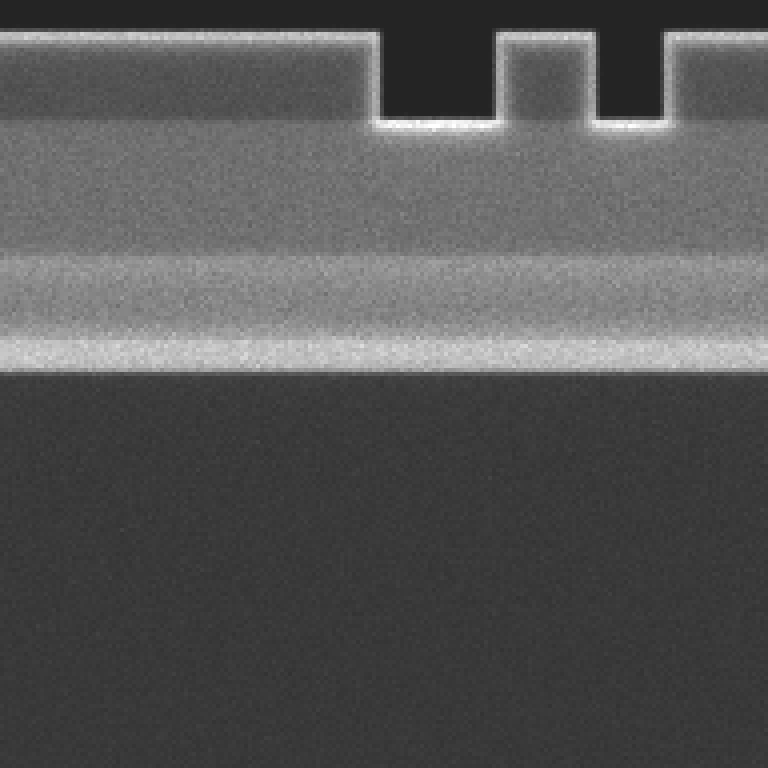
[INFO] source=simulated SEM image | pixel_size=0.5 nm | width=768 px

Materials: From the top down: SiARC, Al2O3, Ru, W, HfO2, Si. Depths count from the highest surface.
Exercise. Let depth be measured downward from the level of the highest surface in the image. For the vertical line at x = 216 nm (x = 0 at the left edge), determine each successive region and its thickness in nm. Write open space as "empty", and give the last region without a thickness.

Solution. empty 44, Al2O3 68, Ru 34, W 8, HfO2 16, Si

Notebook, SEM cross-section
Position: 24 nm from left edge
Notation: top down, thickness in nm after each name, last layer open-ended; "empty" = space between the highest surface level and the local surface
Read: SiARC 44, Al2O3 68, Ru 34, W 8, HfO2 16, Si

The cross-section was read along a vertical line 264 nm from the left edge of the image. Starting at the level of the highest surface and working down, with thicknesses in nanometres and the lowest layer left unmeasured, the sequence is SiARC 44, Al2O3 68, Ru 34, W 8, HfO2 16, Si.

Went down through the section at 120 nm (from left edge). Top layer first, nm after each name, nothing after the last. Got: SiARC 44, Al2O3 68, Ru 34, W 8, HfO2 16, Si